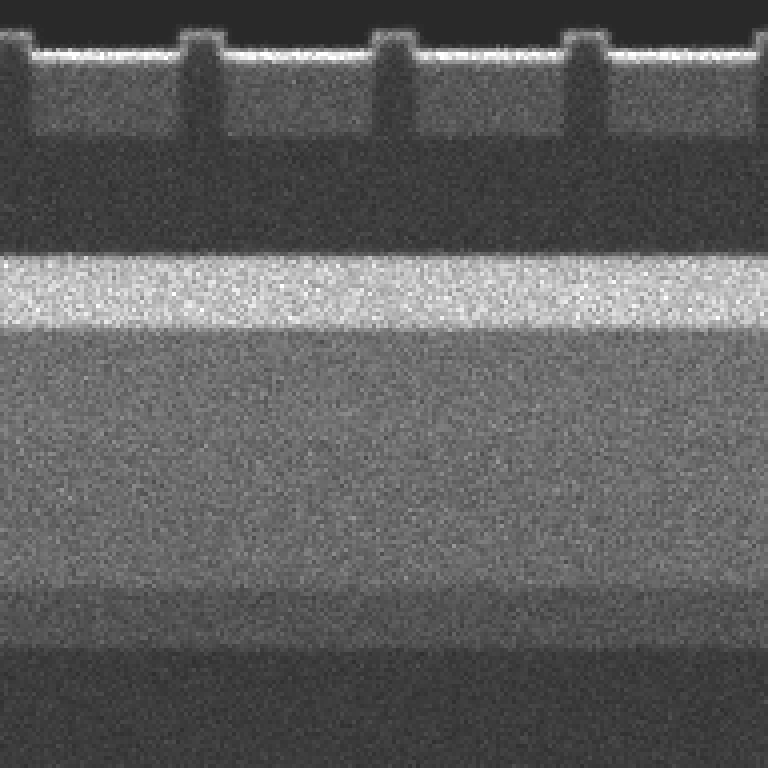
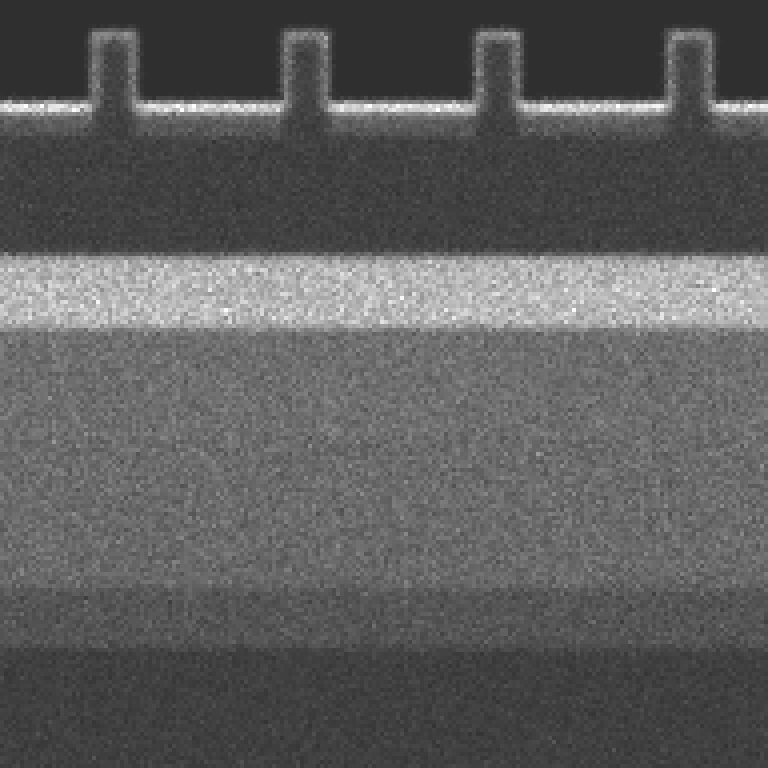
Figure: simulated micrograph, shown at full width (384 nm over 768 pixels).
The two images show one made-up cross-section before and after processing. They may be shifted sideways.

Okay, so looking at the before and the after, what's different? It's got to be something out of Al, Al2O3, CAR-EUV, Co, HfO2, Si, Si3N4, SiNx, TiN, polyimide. Si3N4, removed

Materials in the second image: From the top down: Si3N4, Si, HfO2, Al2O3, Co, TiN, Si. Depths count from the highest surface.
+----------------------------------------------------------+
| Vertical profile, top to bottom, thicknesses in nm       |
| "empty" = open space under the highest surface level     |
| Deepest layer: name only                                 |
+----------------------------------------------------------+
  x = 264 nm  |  empty 36, Si3N4 16, Si 60, HfO2 36, Al2O3 54, Co 76, TiN 30, Si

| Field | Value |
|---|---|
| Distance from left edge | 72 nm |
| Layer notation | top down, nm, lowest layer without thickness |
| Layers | empty 36, Si3N4 16, Si 60, HfO2 36, Al2O3 54, Co 76, TiN 30, Si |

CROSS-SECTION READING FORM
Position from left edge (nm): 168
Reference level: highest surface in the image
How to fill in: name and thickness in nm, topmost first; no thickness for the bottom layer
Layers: empty 36, Si3N4 16, Si 60, HfO2 36, Al2O3 54, Co 76, TiN 30, Si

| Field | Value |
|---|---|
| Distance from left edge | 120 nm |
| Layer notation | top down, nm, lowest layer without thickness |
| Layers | empty 36, Si3N4 16, Si 60, HfO2 36, Al2O3 54, Co 76, TiN 30, Si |